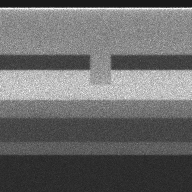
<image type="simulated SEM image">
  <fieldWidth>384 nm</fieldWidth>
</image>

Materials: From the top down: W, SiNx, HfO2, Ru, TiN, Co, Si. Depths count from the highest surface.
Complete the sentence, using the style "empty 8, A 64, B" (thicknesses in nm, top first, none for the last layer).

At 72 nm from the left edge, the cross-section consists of W 94, SiNx 30, HfO2 60, Ru 36, TiN 48, Co 26, Si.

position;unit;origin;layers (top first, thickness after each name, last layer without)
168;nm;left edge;W 94, SiNx 30, HfO2 60, Ru 36, TiN 48, Co 26, Si